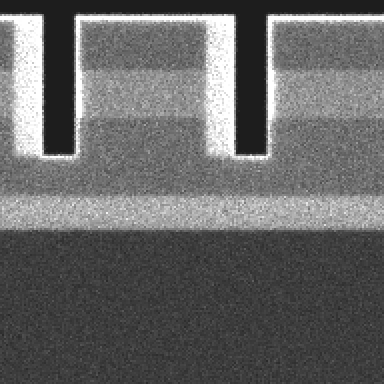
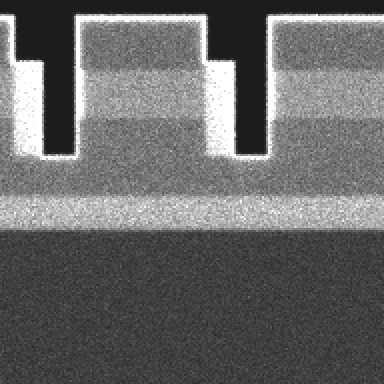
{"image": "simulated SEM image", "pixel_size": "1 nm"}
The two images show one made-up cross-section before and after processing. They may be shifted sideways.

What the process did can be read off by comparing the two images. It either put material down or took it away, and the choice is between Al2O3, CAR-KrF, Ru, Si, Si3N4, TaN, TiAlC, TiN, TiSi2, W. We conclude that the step removed W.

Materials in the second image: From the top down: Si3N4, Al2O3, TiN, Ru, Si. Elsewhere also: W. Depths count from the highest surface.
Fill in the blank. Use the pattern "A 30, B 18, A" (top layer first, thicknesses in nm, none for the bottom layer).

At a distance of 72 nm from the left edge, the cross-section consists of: empty 140, TiN 40, Ru 34, Si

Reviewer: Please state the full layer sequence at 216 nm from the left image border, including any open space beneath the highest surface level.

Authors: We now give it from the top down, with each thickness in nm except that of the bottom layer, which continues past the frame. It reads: empty 46, W 94, TiN 40, Ru 34, Si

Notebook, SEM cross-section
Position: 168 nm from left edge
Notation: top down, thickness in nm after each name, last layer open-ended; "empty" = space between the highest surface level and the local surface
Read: Si3N4 54, Al2O3 48, TiN 78, Ru 34, Si